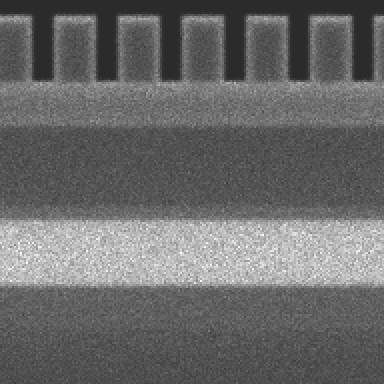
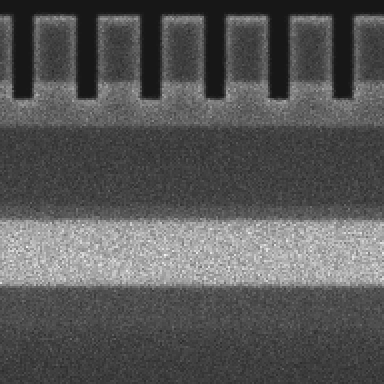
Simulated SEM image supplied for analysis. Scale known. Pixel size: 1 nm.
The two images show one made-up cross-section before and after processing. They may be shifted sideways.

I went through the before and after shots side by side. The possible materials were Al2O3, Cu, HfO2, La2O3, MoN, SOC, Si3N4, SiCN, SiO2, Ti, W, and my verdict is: removed, W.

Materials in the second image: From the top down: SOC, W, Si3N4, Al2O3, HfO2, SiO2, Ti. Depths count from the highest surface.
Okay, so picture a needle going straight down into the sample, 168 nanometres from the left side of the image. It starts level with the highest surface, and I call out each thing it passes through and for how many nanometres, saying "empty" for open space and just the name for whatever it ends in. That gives SOC 66, W 44, Si3N4 80, Al2O3 14, HfO2 66, SiO2 42, Ti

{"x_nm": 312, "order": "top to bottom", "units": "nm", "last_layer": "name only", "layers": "SOC 66, W 44, Si3N4 80, Al2O3 14, HfO2 66, SiO2 42, Ti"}